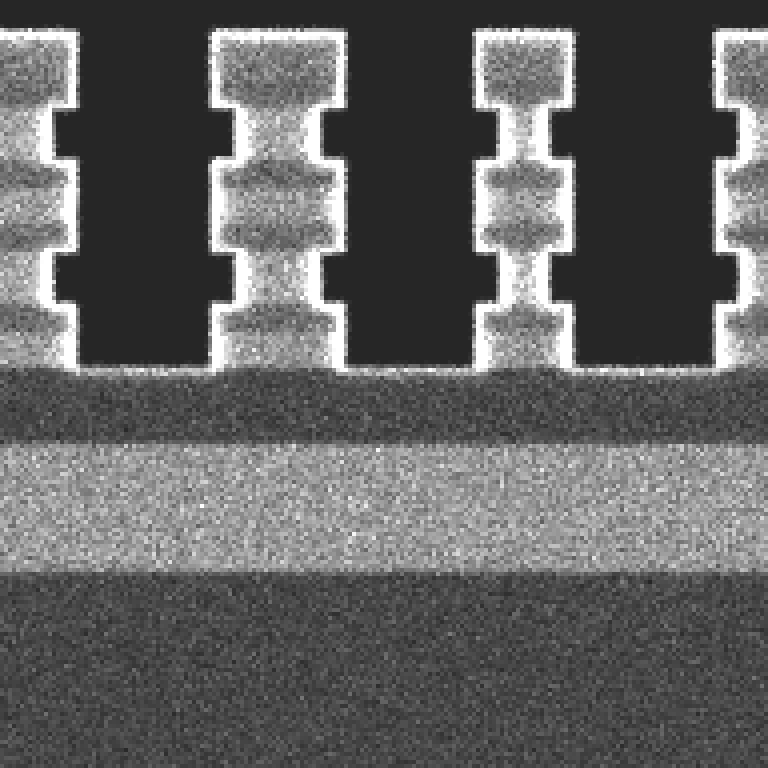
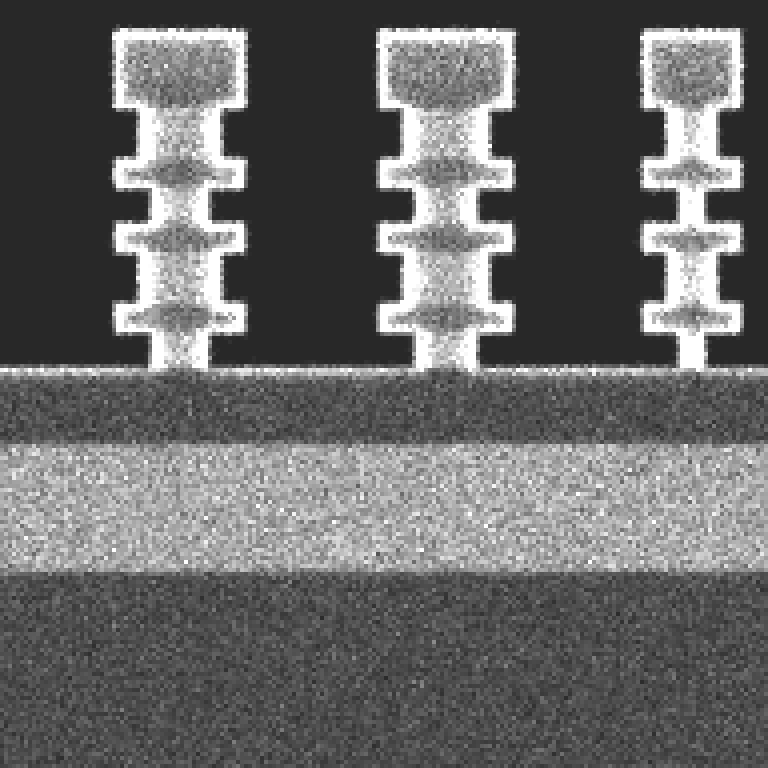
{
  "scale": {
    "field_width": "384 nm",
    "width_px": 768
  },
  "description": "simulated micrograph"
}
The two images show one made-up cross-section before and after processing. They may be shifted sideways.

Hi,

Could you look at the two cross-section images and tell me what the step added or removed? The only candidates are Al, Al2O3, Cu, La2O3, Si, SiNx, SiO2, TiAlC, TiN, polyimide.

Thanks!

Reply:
removed SiO2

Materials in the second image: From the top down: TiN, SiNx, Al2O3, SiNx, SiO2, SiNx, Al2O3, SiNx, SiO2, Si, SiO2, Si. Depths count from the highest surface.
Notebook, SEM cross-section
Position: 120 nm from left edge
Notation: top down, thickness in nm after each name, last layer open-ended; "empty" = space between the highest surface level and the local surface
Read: TiN 24, SiNx 14, empty 26, SiNx 14, empty 18, SiNx 14, empty 26, SiNx 14, empty 18, Si 38, SiO2 64, Si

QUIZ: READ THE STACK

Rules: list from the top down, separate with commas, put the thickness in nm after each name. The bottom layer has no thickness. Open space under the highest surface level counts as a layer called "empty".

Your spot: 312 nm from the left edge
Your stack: empty 168, Si 38, SiO2 64, Si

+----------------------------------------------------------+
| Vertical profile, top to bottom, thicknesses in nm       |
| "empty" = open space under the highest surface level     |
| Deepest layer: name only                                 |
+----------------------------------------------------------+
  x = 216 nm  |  TiN 24, SiNx 14, Al2O3 26, SiNx 14, SiO2 18, SiNx 14, Al2O3 26, SiNx 14, SiO2 18, Si 38, SiO2 64, Si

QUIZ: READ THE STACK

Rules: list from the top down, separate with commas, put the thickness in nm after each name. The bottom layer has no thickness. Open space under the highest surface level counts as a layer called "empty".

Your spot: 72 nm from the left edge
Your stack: TiN 24, SiNx 14, Al2O3 26, SiNx 14, empty 18, SiNx 14, Al2O3 26, SiNx 14, empty 18, Si 38, SiO2 64, Si